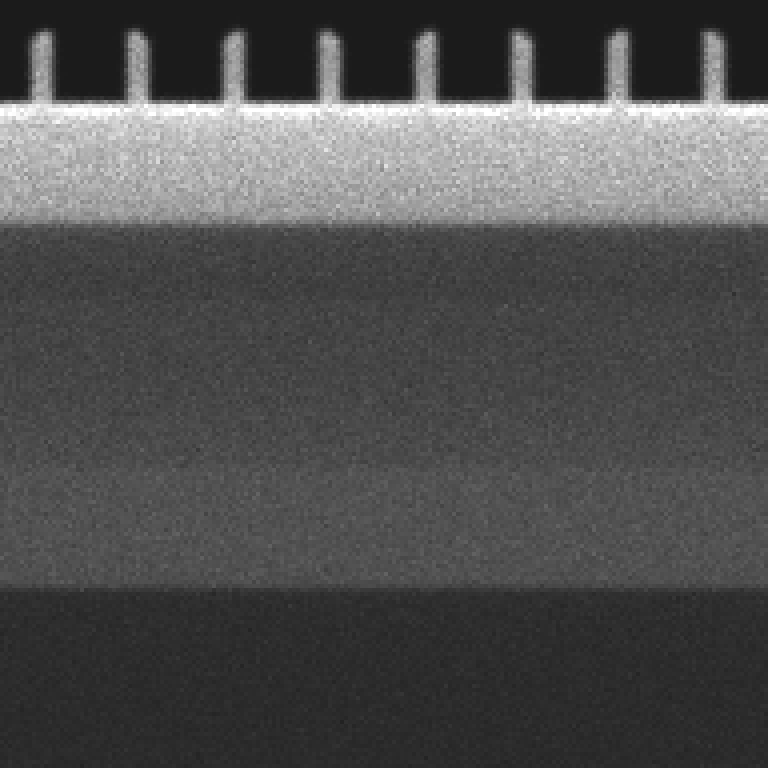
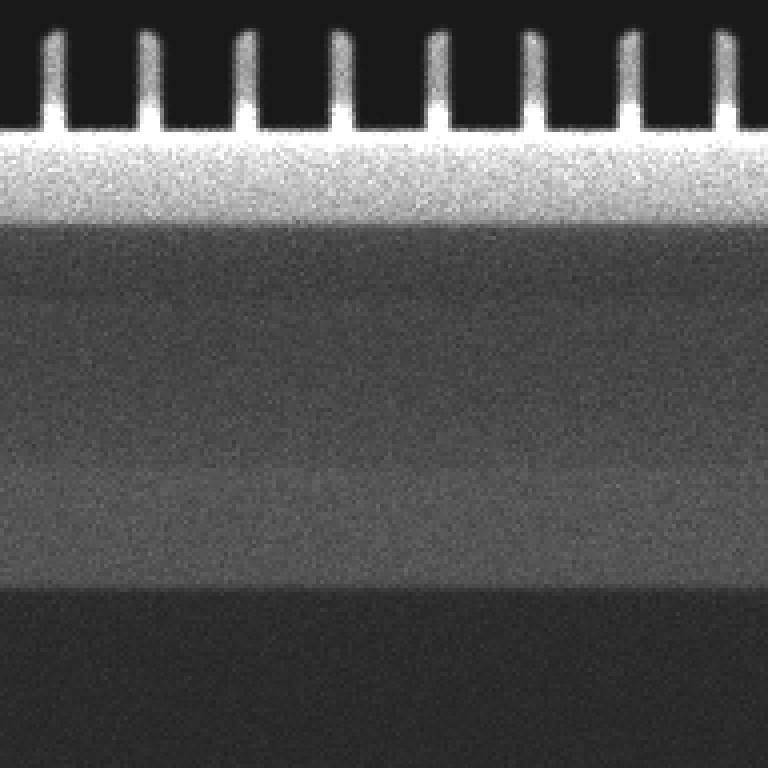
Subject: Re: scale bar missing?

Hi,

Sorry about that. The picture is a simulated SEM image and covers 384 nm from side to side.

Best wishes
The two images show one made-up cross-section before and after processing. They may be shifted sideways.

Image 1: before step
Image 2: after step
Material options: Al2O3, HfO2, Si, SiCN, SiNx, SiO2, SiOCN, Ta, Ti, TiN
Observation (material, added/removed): HfO2, removed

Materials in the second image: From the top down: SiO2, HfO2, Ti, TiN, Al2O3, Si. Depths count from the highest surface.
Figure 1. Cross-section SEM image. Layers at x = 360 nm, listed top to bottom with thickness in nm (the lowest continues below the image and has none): SiO2 36, HfO2 60, Ti 38, TiN 84, Al2O3 60, Si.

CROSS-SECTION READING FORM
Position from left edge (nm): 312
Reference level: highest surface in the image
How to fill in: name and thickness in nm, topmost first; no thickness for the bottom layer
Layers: empty 2, SiO2 34, HfO2 60, Ti 38, TiN 84, Al2O3 60, Si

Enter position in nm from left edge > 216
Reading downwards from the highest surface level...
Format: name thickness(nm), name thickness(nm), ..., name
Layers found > empty 2, SiO2 34, HfO2 60, Ti 38, TiN 84, Al2O3 60, Si